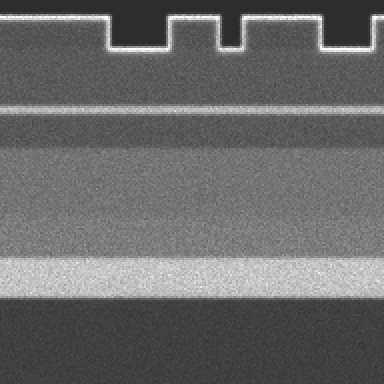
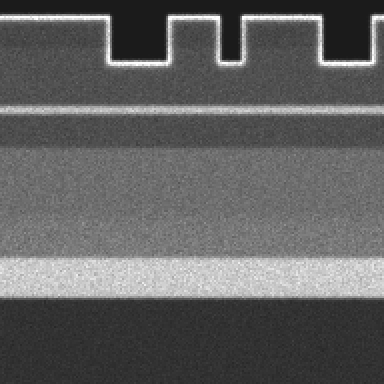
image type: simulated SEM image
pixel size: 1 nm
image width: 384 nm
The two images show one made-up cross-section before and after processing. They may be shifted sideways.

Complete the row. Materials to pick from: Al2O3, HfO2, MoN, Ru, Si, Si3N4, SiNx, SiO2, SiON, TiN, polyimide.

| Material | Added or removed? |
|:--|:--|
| Si3N4 | removed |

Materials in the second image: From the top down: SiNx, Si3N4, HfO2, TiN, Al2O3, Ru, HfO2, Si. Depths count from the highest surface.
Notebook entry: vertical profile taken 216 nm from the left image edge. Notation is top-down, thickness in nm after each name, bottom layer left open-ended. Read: SiNx 32, Si3N4 58, HfO2 8, TiN 34, Al2O3 68, Ru 42, HfO2 40, Si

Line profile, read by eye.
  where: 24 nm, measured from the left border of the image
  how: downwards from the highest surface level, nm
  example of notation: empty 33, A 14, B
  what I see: SiNx 32, Si3N4 58, HfO2 8, TiN 34, Al2O3 68, Ru 42, HfO2 40, Si